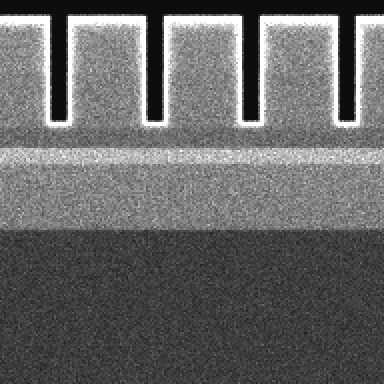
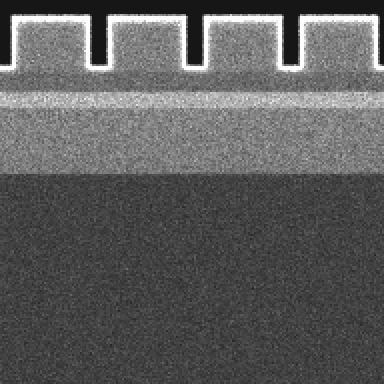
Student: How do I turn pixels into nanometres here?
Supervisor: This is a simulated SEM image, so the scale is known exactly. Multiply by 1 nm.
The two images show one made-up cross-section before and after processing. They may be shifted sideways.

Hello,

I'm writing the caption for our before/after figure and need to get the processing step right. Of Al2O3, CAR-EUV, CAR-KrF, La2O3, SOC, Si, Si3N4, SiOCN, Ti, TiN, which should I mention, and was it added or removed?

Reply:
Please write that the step removed SOC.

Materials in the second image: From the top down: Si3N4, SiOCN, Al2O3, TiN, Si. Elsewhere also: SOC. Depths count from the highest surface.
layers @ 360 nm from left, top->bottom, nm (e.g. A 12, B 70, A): Si3N4 56, SiOCN 20, Al2O3 16, TiN 66, Si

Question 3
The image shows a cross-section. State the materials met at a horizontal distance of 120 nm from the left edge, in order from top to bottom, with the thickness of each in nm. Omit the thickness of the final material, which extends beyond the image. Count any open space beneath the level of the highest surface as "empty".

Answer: Si3N4 56, SiOCN 20, Al2O3 16, TiN 66, Si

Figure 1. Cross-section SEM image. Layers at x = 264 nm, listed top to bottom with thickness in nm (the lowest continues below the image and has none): Si3N4 56, SiOCN 20, Al2O3 16, TiN 66, Si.